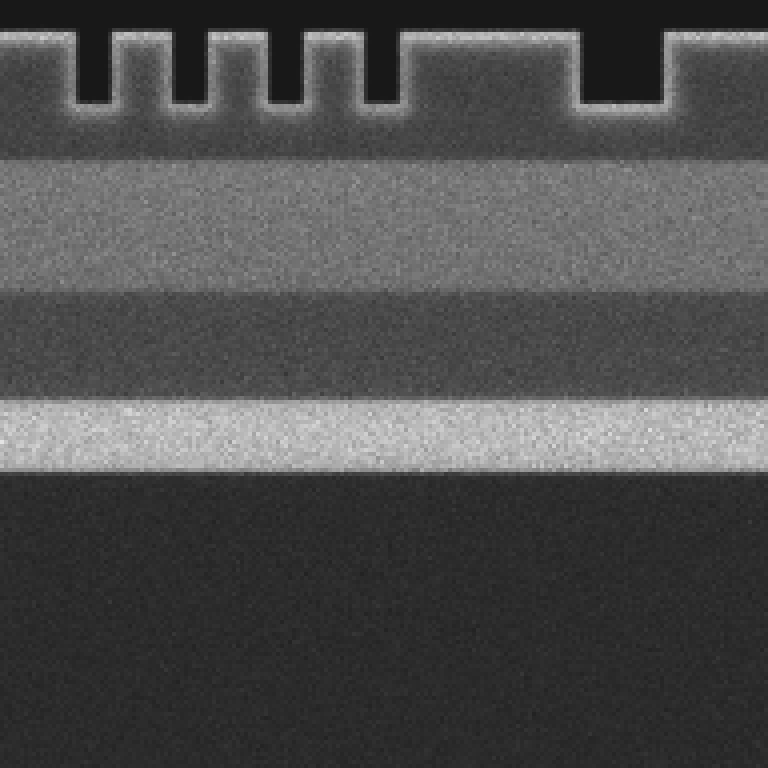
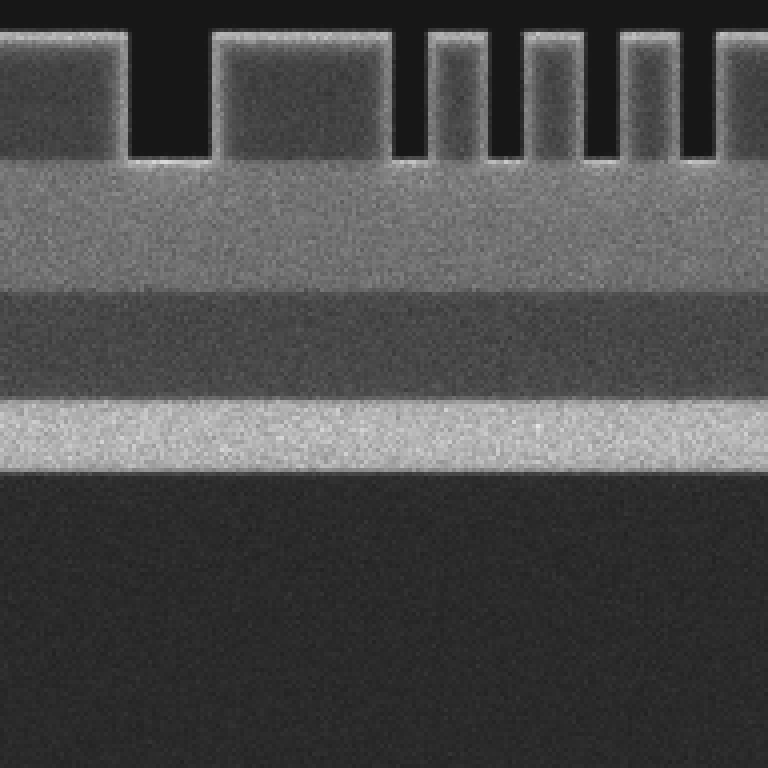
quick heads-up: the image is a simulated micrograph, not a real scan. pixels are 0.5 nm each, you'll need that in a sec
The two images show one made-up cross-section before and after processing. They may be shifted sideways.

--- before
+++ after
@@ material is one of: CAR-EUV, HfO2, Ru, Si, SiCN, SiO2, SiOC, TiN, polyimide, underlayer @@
underlayer removed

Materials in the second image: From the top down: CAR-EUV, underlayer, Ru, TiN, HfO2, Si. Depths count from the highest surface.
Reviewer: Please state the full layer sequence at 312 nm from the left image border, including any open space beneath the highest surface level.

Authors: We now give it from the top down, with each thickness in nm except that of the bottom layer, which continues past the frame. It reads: CAR-EUV 36, underlayer 28, Ru 66, TiN 54, HfO2 36, Si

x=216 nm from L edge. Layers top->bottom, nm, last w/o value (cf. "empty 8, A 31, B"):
CAR-EUV 36, underlayer 28, Ru 66, TiN 54, HfO2 36, Si